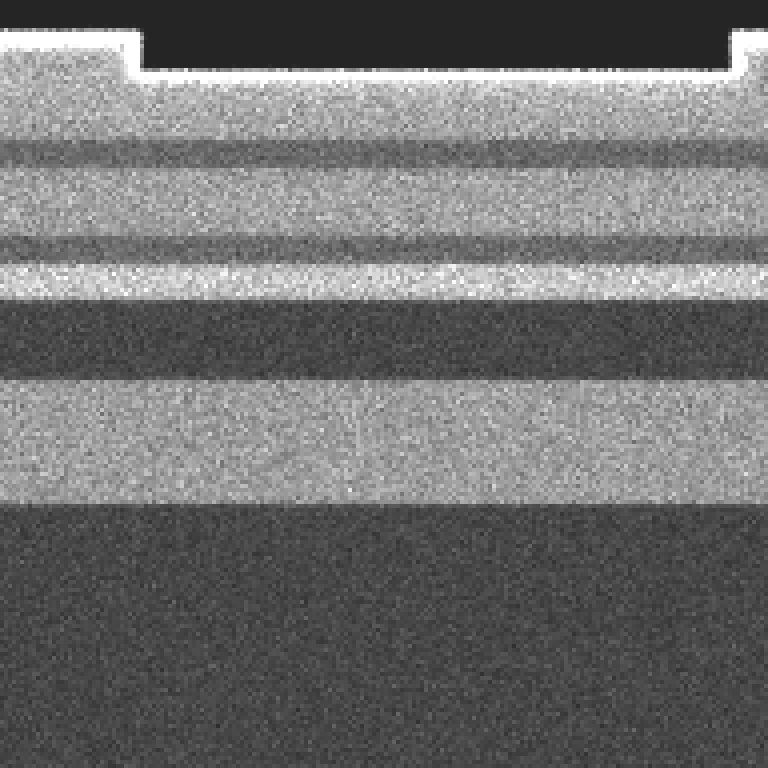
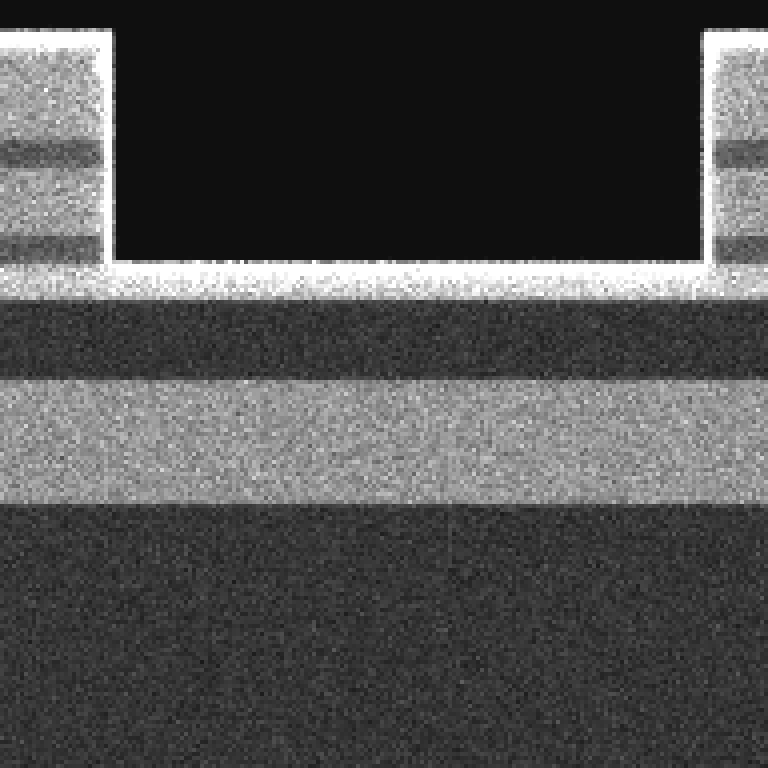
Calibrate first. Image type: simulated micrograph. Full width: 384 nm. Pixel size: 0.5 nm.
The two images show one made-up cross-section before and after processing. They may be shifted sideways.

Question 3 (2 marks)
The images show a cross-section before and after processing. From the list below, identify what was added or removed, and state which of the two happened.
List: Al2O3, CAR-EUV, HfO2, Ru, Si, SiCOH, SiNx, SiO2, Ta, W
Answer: Ru and SiNx was removed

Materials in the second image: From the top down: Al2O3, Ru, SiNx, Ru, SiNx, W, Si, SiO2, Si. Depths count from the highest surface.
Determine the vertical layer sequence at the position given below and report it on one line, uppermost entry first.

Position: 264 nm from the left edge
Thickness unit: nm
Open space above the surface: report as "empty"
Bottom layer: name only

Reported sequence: empty 116, W 18, Si 40, SiO2 62, Si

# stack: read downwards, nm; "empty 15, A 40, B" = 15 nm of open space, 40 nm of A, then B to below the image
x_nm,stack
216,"empty 116, W 18, Si 40, SiO2 62, Si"